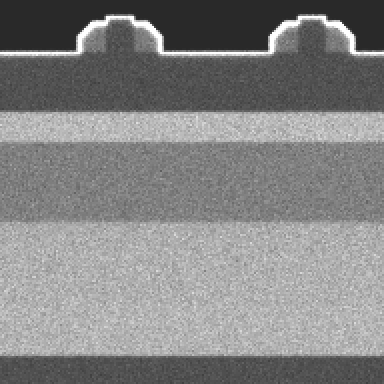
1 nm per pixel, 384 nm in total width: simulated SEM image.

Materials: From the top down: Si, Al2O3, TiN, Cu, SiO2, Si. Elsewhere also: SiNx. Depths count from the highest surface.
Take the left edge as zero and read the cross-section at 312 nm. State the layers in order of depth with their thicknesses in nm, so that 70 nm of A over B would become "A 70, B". Si 96, Al2O3 30, TiN 80, Cu 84, SiO2 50, Si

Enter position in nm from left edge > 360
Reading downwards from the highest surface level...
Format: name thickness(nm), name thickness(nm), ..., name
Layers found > empty 36, Si 60, Al2O3 30, TiN 80, Cu 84, SiO2 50, Si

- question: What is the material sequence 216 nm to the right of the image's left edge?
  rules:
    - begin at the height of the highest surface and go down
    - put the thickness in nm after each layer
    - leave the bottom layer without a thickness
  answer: empty 36, Si 60, Al2O3 30, TiN 80, Cu 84, SiO2 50, Si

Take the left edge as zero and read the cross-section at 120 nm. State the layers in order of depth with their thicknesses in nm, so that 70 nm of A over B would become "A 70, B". Si 96, Al2O3 30, TiN 80, Cu 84, SiO2 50, Si